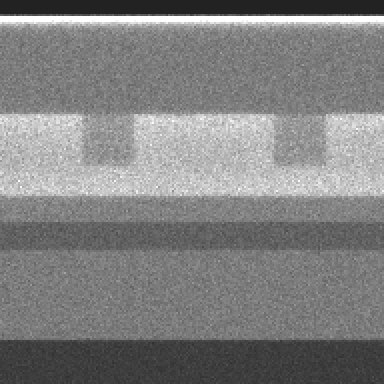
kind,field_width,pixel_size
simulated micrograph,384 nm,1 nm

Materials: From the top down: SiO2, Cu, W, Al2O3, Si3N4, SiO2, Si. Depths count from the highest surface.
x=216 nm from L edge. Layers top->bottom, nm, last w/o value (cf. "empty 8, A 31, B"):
SiO2 98, W 82, Al2O3 26, Si3N4 28, SiO2 90, Si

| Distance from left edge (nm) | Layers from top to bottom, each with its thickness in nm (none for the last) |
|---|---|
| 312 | SiO2 98, Cu 52, W 30, Al2O3 26, Si3N4 28, SiO2 90, Si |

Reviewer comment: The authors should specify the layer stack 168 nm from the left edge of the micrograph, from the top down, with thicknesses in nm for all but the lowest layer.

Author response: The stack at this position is SiO2 98, W 82, Al2O3 26, Si3N4 28, SiO2 90, Si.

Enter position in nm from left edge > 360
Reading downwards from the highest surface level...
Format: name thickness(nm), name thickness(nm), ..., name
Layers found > SiO2 98, W 82, Al2O3 26, Si3N4 28, SiO2 90, Si